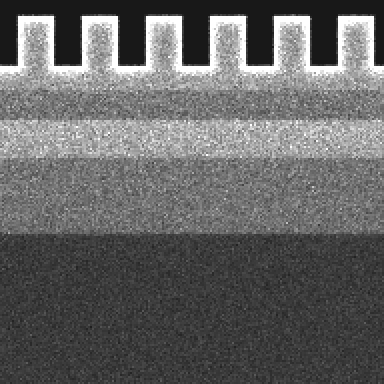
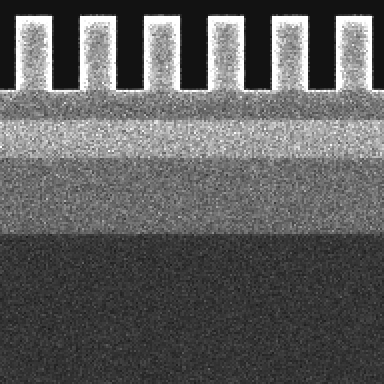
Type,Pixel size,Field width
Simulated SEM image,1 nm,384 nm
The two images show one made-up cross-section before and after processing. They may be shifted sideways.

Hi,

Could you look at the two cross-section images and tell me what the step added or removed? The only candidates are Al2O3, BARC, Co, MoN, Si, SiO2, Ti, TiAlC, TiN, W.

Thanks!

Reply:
removed Al2O3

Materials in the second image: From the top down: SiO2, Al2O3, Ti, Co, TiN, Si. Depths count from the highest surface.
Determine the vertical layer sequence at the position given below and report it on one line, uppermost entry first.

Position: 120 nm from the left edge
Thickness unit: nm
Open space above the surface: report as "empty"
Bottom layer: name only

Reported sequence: empty 74, Ti 30, Co 38, TiN 76, Si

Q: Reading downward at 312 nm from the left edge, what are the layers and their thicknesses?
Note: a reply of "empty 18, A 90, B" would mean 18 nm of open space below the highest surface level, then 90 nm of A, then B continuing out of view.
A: empty 74, Ti 30, Co 38, TiN 76, Si